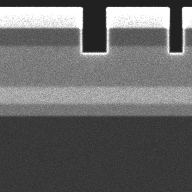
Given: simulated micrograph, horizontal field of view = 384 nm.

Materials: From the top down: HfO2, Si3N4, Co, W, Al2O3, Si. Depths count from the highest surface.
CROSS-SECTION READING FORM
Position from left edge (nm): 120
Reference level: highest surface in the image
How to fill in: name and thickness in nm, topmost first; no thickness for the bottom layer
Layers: HfO2 40, Si3N4 36, Co 82, W 34, Al2O3 24, Si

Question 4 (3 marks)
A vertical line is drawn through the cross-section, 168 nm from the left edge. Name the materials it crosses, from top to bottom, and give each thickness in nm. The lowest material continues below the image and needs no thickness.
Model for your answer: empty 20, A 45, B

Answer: empty 90, Co 68, W 34, Al2O3 24, Si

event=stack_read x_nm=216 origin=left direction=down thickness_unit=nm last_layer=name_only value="HfO2 40, Si3N4 36, Co 82, W 34, Al2O3 24, Si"